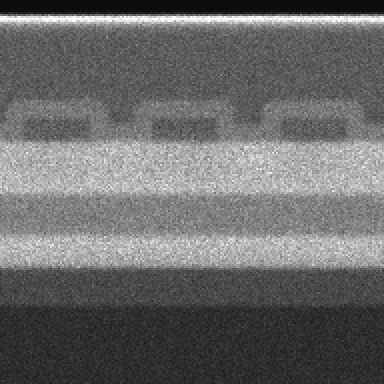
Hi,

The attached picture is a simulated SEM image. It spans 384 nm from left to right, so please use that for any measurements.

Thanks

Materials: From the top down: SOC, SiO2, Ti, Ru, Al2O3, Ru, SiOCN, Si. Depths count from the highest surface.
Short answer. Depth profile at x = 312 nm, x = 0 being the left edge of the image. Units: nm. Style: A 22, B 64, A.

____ SOC 84, SiO2 18, Ti 24, Ru 52, Al2O3 42, Ru 32, SiOCN 38, Si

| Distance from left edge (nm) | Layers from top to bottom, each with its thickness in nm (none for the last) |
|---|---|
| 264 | SOC 90, SiO2 36, Ru 52, Al2O3 42, Ru 32, SiOCN 38, Si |